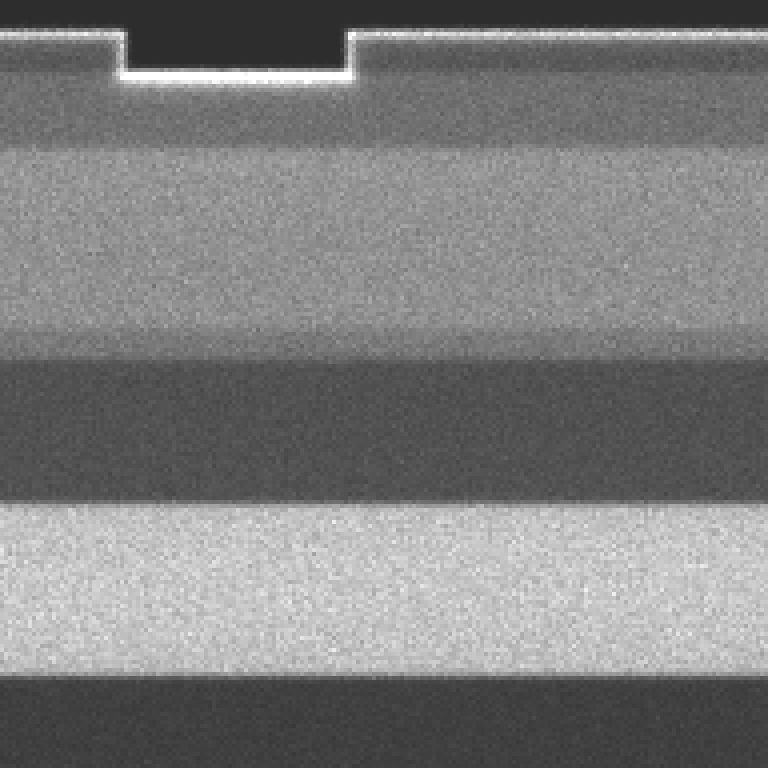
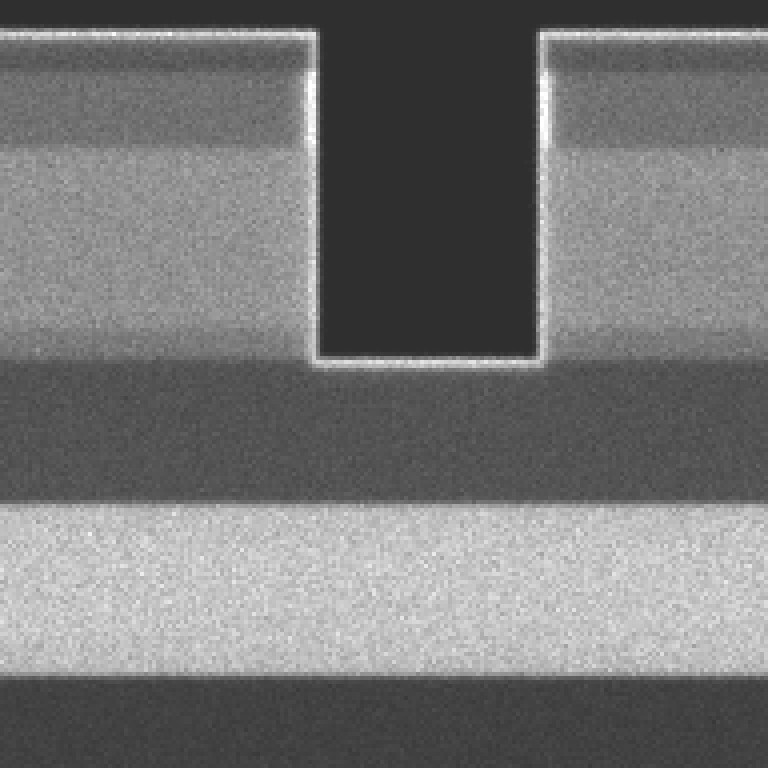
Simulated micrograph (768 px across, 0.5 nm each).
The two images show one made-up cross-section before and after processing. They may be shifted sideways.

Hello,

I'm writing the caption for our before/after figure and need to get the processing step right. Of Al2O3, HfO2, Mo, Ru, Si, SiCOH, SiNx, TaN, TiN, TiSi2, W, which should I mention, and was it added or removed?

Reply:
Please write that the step removed Al2O3 and Ru and W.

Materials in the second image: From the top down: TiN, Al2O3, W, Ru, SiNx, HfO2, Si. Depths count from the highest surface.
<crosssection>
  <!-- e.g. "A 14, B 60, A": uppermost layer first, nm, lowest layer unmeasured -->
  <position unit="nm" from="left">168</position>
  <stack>empty 164, SiNx 72, HfO2 86, Si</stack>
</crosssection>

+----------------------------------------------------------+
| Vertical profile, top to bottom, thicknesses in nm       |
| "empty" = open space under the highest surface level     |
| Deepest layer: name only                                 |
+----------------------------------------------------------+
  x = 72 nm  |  TiN 20, Al2O3 38, W 90, Ru 16, SiNx 72, HfO2 86, Si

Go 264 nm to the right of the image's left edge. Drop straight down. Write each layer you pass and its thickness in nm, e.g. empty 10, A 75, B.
empty 164, SiNx 72, HfO2 86, Si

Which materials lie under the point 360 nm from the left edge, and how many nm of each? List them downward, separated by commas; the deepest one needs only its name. TiN 20, Al2O3 38, W 90, Ru 16, SiNx 72, HfO2 86, Si